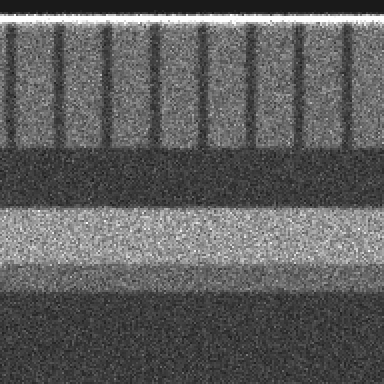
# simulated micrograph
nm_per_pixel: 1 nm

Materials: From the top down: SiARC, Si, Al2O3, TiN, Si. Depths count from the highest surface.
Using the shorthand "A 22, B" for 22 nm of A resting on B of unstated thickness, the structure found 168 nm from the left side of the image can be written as SiARC 132, Si 60, Al2O3 56, TiN 28, Si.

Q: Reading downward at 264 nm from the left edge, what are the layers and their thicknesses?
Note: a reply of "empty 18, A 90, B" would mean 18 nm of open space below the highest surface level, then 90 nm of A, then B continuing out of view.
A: SiARC 132, Si 60, Al2O3 56, TiN 28, Si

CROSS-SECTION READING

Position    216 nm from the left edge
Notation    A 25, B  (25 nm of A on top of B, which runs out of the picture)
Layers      SiARC 132, Si 60, Al2O3 56, TiN 28, Si